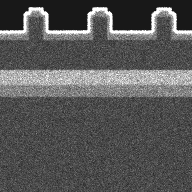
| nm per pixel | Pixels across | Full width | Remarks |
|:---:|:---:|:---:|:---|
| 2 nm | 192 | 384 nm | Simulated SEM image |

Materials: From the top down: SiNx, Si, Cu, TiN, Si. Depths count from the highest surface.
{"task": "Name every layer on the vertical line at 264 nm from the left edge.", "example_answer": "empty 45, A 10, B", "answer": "empty 46, SiNx 18, Si 60, Cu 30, TiN 24, Si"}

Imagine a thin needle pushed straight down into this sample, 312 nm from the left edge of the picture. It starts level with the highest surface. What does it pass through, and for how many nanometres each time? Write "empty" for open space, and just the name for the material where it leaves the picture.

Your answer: empty 8, SiNx 56, Si 60, Cu 30, TiN 24, Si